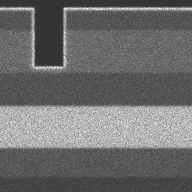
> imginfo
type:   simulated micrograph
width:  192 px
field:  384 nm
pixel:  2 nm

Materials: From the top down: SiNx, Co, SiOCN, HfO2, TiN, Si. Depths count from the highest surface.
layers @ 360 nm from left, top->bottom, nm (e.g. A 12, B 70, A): SiNx 44, Co 86, SiOCN 66, HfO2 84, TiN 58, Si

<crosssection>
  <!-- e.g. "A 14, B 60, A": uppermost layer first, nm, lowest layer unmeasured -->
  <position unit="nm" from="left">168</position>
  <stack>SiNx 44, Co 86, SiOCN 66, HfO2 84, TiN 58, Si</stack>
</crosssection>